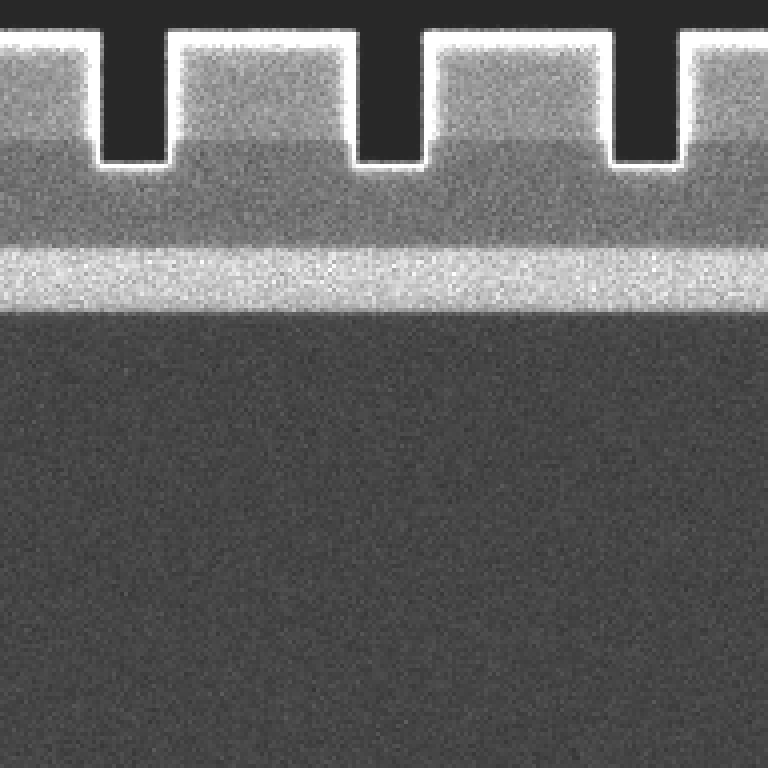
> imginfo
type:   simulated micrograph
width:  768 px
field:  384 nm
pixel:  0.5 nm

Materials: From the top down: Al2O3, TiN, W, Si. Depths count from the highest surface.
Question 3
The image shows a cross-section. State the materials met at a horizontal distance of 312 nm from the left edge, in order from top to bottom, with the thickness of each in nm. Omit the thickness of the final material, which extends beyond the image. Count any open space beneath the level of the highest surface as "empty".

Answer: empty 66, TiN 42, W 32, Si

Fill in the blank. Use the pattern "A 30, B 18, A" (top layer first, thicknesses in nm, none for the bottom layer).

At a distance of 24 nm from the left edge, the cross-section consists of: Al2O3 54, TiN 54, W 32, Si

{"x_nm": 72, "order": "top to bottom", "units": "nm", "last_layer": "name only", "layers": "empty 66, TiN 42, W 32, Si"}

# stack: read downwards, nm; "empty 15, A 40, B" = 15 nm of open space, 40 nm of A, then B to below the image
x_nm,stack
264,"Al2O3 54, TiN 54, W 32, Si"